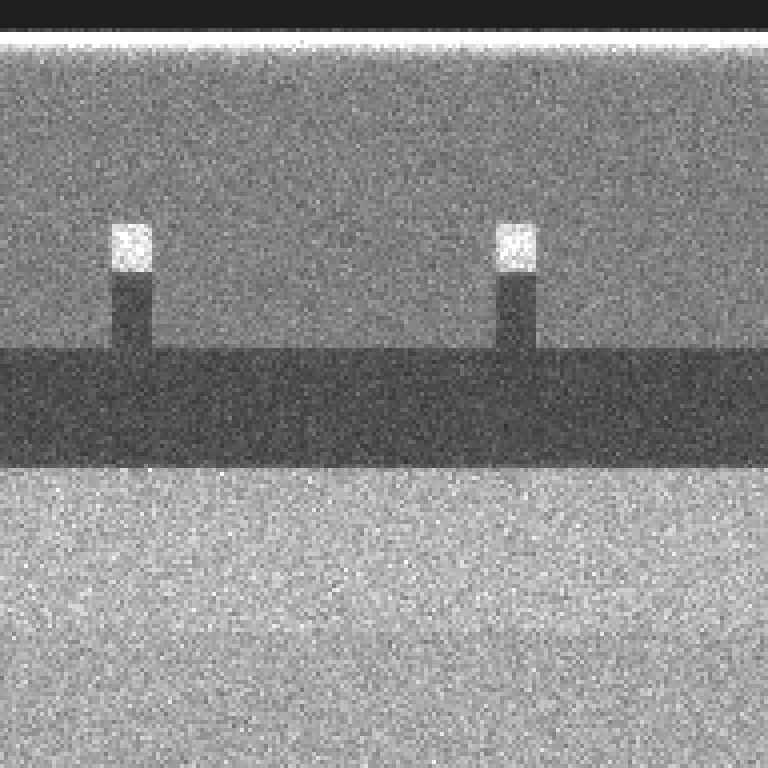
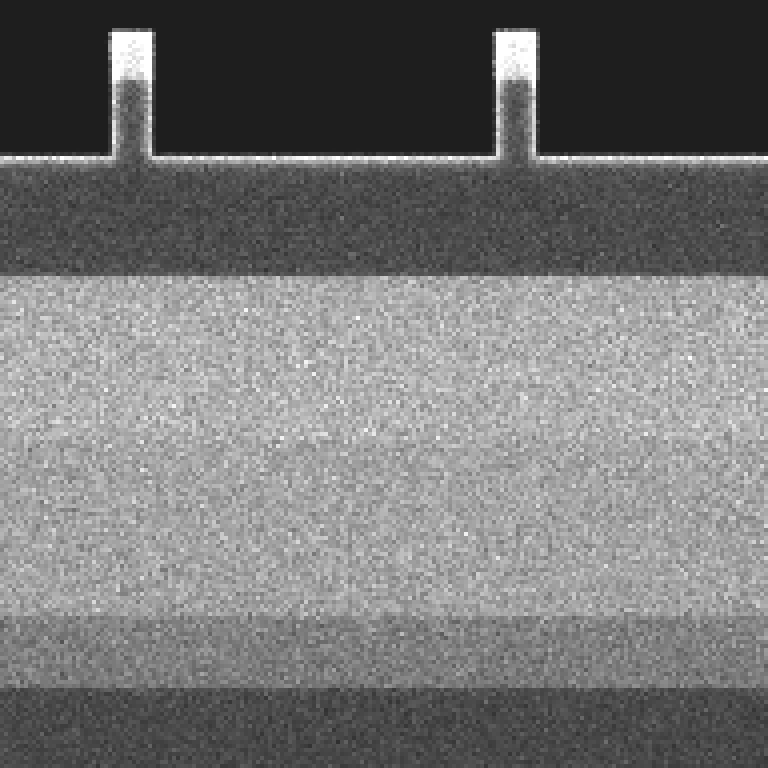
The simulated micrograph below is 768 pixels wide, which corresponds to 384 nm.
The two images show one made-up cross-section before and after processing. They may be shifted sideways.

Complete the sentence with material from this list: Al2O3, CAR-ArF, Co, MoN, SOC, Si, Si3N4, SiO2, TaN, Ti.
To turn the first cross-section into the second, SOC must be removed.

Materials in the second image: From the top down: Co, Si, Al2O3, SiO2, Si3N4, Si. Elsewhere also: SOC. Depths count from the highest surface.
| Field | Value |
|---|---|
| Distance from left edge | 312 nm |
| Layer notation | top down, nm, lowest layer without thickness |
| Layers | empty 62, Si 60, Al2O3 82, SiO2 88, Si3N4 36, Si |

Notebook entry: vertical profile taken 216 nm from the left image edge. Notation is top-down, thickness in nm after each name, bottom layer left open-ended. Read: empty 62, Si 60, Al2O3 82, SiO2 88, Si3N4 36, Si